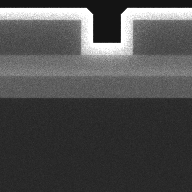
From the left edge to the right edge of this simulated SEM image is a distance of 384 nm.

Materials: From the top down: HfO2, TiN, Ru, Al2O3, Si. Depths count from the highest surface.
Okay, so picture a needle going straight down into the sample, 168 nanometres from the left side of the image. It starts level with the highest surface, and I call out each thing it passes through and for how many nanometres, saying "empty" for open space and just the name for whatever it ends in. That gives HfO2 94, Ru 42, Al2O3 44, Si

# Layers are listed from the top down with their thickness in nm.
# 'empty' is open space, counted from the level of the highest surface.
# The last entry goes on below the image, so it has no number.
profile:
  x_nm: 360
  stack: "HfO2 24, TiN 70, Ru 42, Al2O3 44, Si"